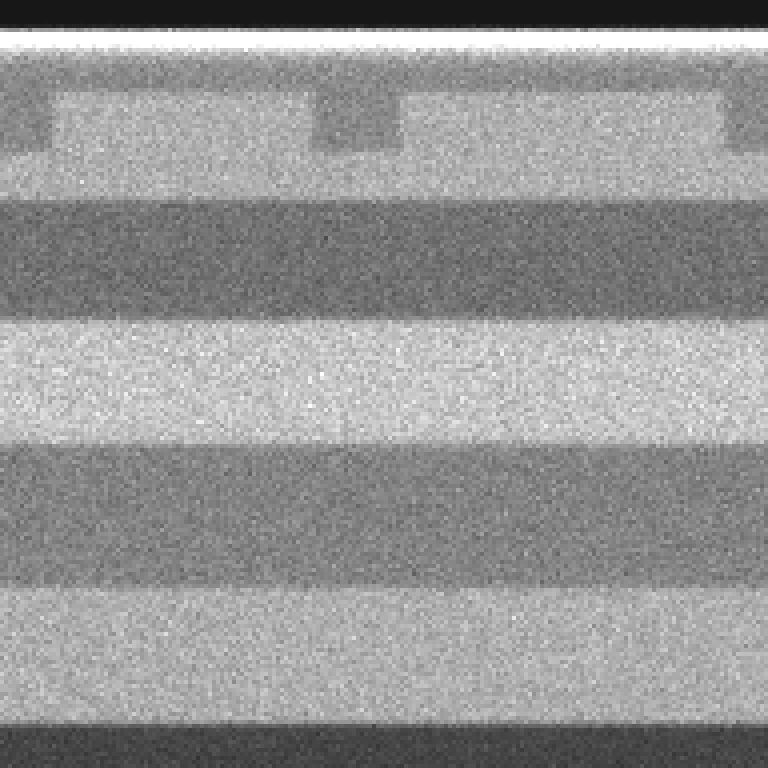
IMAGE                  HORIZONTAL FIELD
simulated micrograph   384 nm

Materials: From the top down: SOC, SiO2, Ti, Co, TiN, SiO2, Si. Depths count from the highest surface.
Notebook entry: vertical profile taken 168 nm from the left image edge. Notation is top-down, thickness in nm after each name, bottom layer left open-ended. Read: SOC 60, SiO2 24, Ti 60, Co 62, TiN 72, SiO2 68, Si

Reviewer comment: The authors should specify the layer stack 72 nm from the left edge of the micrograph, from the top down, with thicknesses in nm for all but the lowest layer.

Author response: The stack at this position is SOC 30, SiO2 54, Ti 60, Co 62, TiN 72, SiO2 68, Si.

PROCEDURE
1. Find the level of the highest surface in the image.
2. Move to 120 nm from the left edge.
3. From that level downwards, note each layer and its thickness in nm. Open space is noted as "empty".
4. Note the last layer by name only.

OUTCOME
SOC 30, SiO2 54, Ti 60, Co 62, TiN 72, SiO2 68, Si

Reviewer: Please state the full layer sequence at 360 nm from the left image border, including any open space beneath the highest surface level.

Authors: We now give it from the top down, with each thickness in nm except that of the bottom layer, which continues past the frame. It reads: SOC 30, SiO2 54, Ti 60, Co 62, TiN 72, SiO2 68, Si